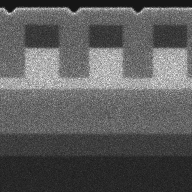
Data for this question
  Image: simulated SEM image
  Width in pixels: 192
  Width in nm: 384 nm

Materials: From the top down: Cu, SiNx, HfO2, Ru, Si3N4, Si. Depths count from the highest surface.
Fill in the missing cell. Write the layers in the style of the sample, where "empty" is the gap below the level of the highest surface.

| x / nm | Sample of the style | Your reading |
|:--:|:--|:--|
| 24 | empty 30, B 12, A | empty 8, Cu 132, HfO2 22, Ru 90, Si3N4 44, Si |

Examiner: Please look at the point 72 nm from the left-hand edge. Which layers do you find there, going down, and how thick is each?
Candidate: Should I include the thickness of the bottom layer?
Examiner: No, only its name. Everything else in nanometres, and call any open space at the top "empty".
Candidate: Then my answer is Cu 34, SiNx 46, HfO2 82, Ru 90, Si3N4 44, Si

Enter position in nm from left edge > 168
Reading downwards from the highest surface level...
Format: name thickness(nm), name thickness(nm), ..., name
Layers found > Cu 140, HfO2 22, Ru 90, Si3N4 44, Si